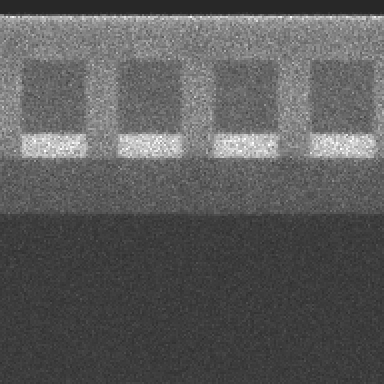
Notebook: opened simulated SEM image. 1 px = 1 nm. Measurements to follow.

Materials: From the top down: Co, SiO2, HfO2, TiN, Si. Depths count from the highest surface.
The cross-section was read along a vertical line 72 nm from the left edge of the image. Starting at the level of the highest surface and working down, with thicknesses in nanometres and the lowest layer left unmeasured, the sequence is Co 44, SiO2 74, HfO2 24, TiN 56, Si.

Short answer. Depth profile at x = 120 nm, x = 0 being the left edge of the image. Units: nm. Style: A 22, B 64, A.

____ Co 44, SiO2 74, HfO2 24, TiN 56, Si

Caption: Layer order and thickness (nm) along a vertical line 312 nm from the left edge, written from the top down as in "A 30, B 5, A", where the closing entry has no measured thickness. Co 44, SiO2 74, HfO2 24, TiN 56, Si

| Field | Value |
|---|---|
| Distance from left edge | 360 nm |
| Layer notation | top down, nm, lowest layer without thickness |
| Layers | Co 44, SiO2 74, HfO2 24, TiN 56, Si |